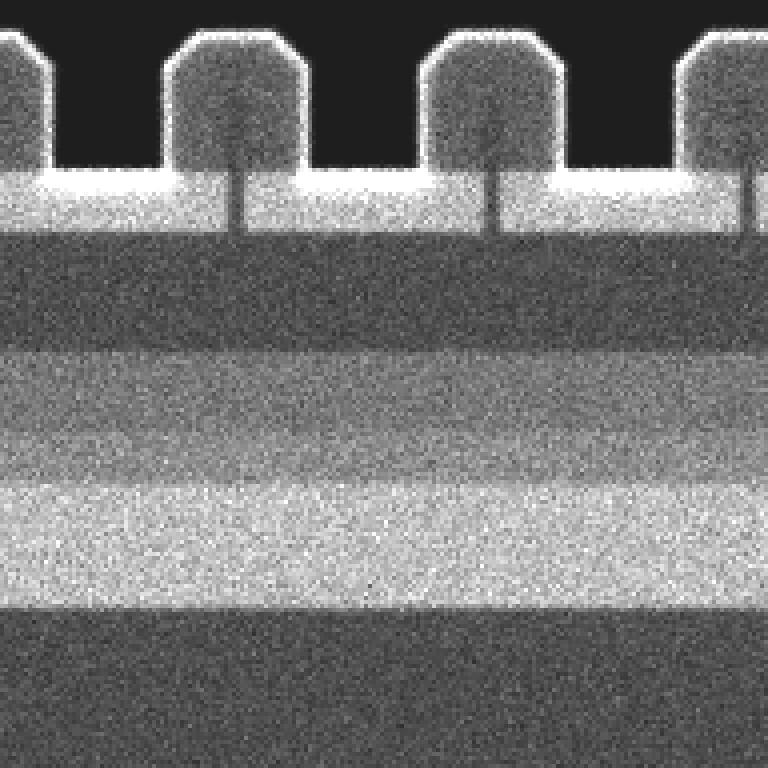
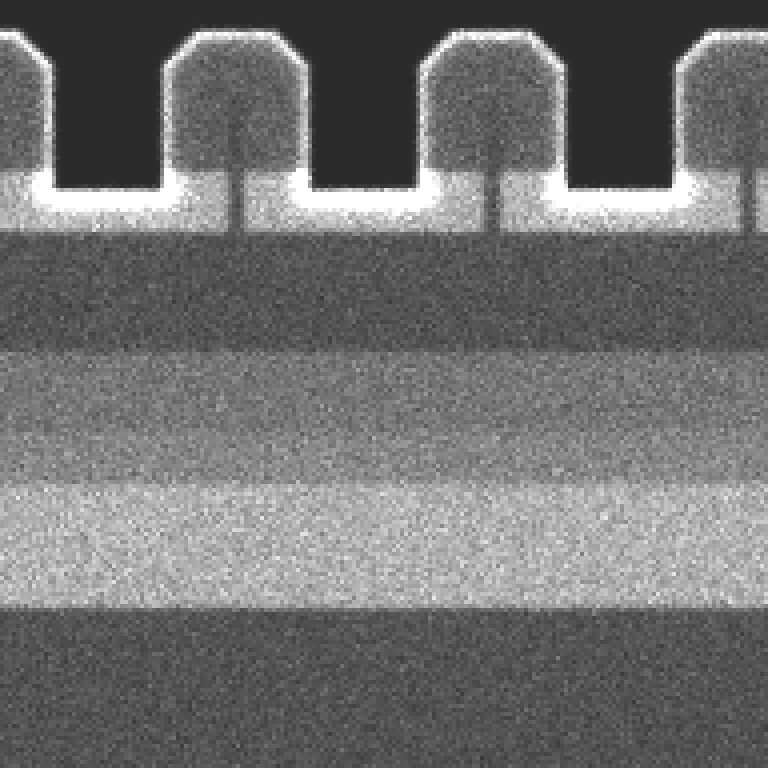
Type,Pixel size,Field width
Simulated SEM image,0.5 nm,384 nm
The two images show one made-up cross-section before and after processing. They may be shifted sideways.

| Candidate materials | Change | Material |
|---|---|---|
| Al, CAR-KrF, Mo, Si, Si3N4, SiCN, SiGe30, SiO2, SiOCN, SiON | removed | SiO2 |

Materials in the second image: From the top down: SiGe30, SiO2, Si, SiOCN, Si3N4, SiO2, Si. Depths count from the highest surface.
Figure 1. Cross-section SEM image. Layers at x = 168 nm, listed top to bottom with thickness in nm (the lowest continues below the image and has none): empty 80, SiO2 20, Si 60, SiOCN 40, Si3N4 26, SiO2 62, Si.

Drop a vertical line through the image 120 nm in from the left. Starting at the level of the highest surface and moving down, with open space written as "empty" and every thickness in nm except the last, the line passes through SiGe30 32, Si 128, SiOCN 40, Si3N4 26, SiO2 62, Si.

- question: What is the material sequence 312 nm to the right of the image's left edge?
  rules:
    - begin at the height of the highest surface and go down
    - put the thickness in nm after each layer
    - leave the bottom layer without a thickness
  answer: empty 80, SiO2 20, Si 60, SiOCN 40, Si3N4 26, SiO2 62, Si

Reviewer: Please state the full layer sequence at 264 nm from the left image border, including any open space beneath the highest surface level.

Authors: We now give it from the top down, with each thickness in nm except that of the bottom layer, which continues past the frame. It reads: SiGe30 70, SiO2 30, Si 60, SiOCN 40, Si3N4 26, SiO2 62, Si